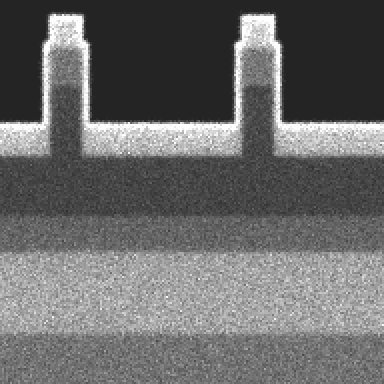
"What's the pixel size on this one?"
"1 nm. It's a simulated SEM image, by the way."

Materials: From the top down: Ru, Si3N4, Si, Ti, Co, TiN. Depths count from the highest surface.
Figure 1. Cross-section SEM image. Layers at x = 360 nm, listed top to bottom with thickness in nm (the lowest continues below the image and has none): empty 108, Ru 32, Si 60, Ti 36, Co 82, TiN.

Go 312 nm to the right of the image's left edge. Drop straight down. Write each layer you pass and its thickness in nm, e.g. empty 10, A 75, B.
empty 108, Ru 32, Si 60, Ti 36, Co 82, TiN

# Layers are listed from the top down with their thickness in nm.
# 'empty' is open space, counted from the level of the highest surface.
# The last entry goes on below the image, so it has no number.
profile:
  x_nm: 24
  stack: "empty 108, Ru 32, Si 60, Ti 36, Co 82, TiN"